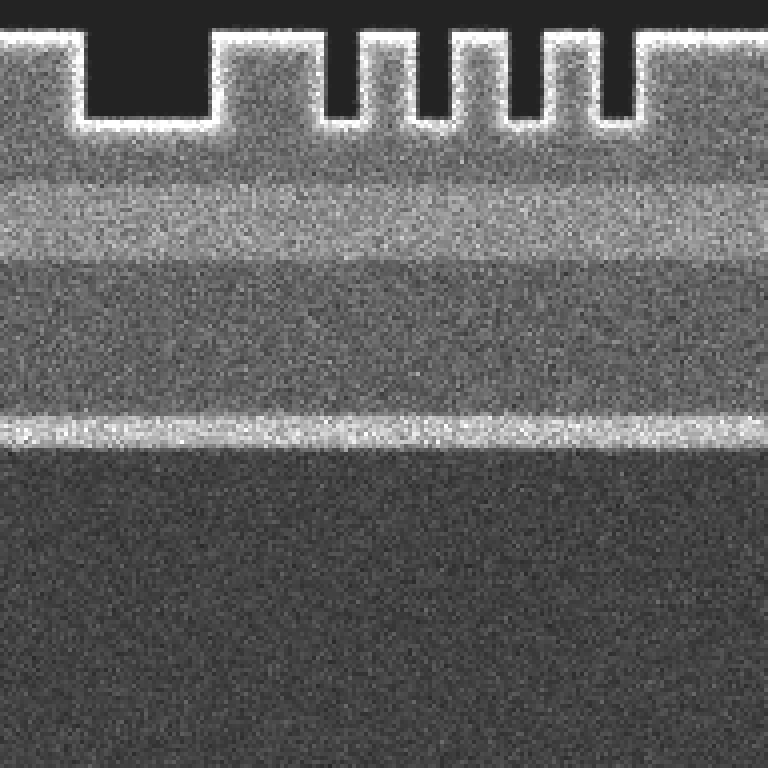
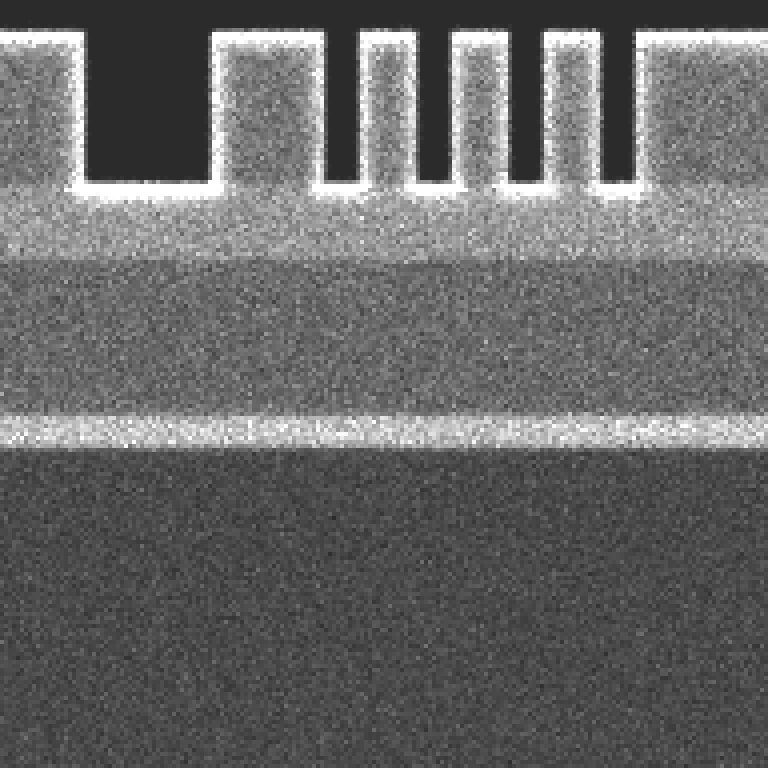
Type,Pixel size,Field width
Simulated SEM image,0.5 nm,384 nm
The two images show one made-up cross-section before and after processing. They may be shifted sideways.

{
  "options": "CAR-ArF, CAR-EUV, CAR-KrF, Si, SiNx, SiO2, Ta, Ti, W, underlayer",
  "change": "removed",
  "material": "underlayer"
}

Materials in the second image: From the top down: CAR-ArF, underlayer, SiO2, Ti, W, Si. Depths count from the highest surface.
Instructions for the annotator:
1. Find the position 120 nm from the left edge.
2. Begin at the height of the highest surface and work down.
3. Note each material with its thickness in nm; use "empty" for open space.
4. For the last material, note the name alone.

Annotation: CAR-ArF 44, underlayer 32, SiO2 38, Ti 78, W 16, Si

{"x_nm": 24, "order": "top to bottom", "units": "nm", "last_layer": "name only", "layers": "CAR-ArF 44, underlayer 32, SiO2 38, Ti 78, W 16, Si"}